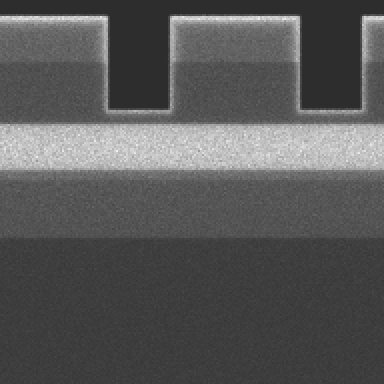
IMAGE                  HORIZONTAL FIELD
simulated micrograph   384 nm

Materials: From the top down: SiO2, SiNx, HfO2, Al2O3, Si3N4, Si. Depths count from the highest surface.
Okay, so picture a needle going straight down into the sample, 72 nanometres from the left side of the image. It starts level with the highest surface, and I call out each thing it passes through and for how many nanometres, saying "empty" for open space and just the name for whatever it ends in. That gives SiO2 46, SiNx 62, HfO2 46, Al2O3 10, Si3N4 58, Si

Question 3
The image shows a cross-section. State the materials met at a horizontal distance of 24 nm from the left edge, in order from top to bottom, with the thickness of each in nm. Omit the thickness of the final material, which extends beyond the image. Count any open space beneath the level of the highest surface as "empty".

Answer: SiO2 46, SiNx 62, HfO2 46, Al2O3 10, Si3N4 58, Si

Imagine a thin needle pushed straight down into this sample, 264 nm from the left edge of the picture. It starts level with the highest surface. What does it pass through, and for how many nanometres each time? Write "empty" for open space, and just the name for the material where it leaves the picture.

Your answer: SiO2 46, SiNx 62, HfO2 46, Al2O3 10, Si3N4 58, Si